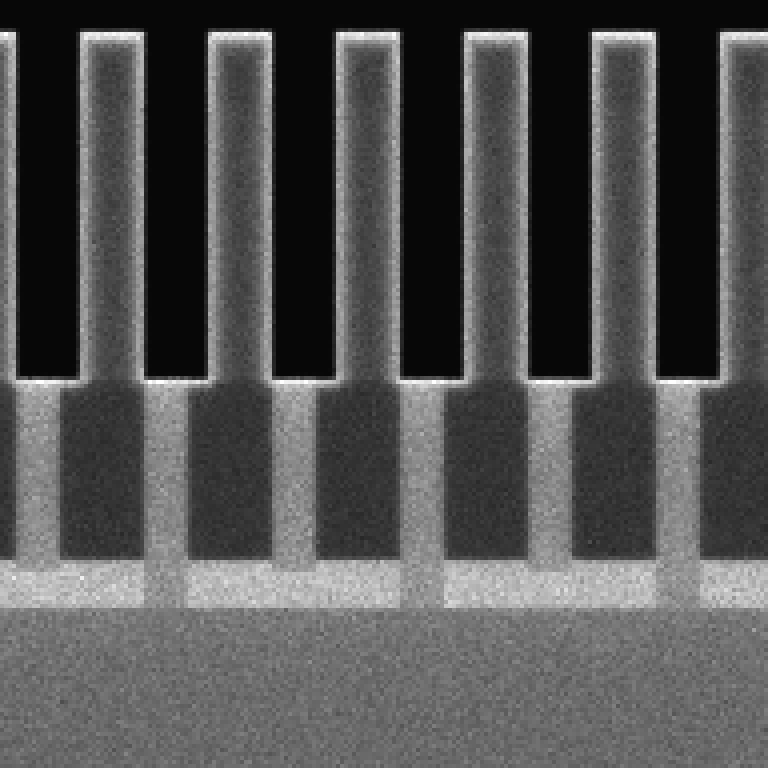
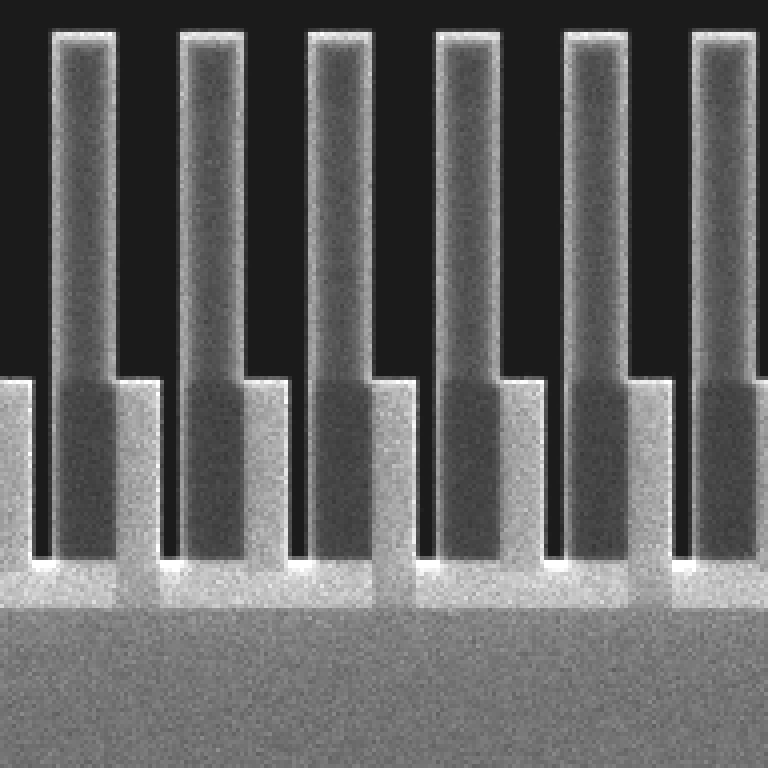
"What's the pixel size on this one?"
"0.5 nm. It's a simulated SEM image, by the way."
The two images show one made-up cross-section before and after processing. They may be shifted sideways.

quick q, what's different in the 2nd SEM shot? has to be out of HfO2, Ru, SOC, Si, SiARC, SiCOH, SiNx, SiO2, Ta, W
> SiNx removed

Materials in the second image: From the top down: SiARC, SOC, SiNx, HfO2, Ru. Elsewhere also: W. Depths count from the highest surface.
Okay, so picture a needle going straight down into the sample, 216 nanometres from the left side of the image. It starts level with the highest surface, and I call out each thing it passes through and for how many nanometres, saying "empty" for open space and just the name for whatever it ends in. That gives empty 264, HfO2 24, Ru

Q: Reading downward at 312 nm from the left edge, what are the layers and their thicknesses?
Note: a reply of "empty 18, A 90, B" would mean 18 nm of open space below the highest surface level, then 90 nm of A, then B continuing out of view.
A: SiARC 36, SOC 138, SiNx 90, HfO2 24, Ru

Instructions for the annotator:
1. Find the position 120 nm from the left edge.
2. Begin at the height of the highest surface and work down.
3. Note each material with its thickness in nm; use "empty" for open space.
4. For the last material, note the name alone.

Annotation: SiARC 36, SOC 138, SiNx 90, HfO2 24, Ru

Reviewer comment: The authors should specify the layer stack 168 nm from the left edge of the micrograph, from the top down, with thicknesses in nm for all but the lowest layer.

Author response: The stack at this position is SiARC 36, SOC 138, SiNx 90, HfO2 24, Ru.